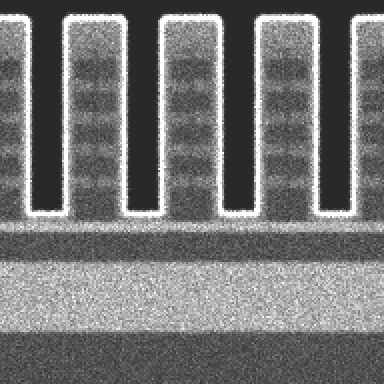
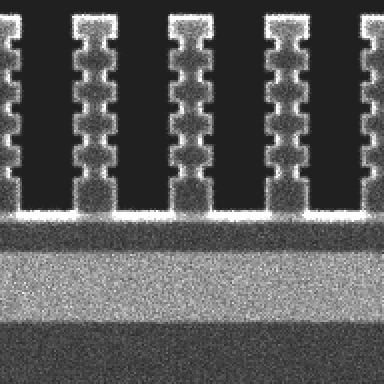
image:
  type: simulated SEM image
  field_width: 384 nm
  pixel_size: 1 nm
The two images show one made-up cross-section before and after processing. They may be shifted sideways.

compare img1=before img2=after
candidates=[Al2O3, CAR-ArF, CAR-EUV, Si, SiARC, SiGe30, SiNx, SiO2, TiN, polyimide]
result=removed:SiNx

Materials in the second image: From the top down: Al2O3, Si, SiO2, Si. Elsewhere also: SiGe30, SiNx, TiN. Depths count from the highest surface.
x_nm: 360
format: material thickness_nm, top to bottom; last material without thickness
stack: empty 196, Al2O3 10, Si 30, SiO2 70, Si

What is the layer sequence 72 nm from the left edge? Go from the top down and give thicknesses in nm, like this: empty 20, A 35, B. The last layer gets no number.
empty 196, Al2O3 10, Si 30, SiO2 70, Si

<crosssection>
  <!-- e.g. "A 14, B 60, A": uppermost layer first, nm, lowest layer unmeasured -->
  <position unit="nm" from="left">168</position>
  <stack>empty 196, Al2O3 10, Si 30, SiO2 70, Si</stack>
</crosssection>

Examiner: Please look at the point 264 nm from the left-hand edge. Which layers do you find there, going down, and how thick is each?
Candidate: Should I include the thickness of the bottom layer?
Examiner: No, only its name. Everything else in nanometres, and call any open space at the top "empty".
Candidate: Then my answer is empty 196, Al2O3 10, Si 30, SiO2 70, Si